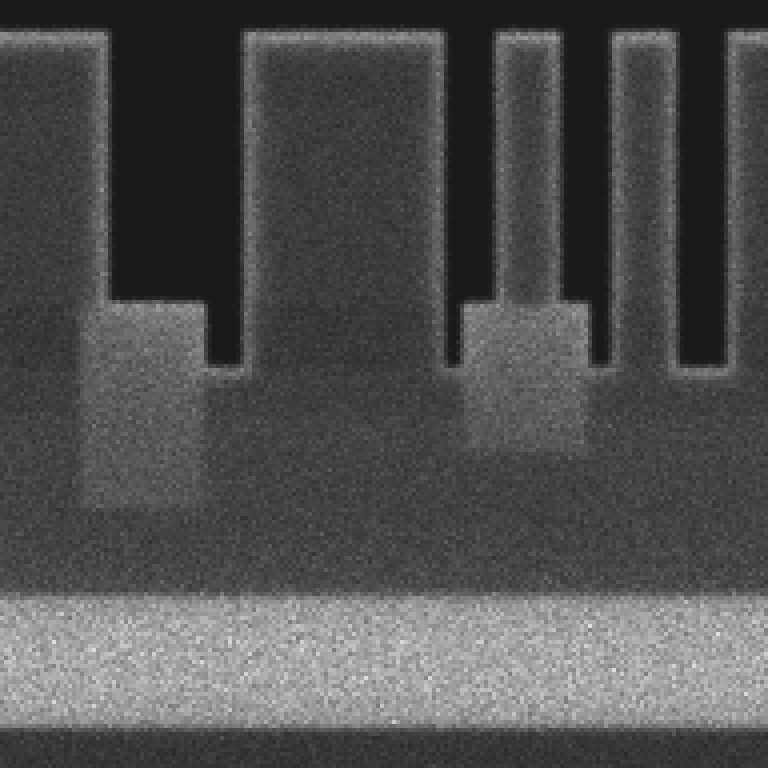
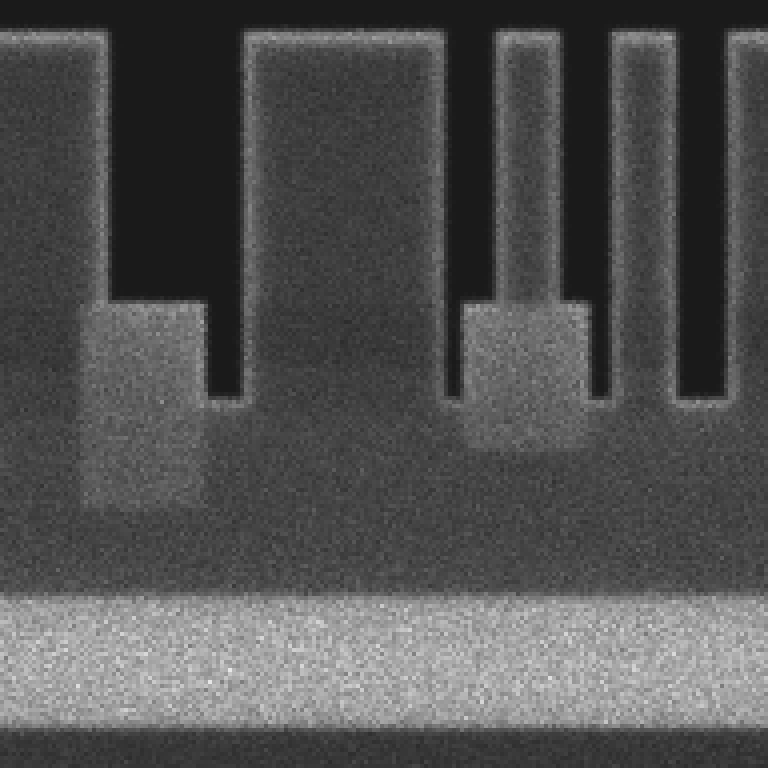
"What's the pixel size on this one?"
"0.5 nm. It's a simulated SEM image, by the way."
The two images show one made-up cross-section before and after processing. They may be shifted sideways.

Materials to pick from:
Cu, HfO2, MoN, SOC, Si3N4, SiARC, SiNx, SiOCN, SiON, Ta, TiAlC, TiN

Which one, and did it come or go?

Si3N4 - removed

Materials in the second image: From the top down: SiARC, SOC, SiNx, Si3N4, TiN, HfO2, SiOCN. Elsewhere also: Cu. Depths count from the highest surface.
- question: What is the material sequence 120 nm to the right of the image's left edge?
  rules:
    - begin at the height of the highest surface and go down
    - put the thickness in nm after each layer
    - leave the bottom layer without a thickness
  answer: empty 184, Si3N4 8, TiN 90, HfO2 66, SiOCN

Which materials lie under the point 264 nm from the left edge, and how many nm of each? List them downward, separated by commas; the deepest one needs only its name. SiARC 38, SOC 98, Cu 74, TiN 72, HfO2 66, SiOCN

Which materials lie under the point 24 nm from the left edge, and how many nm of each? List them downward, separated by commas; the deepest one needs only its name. SiARC 38, SOC 98, SiNx 32, Si3N4 24, TiN 90, HfO2 66, SiOCN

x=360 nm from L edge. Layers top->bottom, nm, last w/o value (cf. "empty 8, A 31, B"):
empty 184, Si3N4 8, TiN 90, HfO2 66, SiOCN